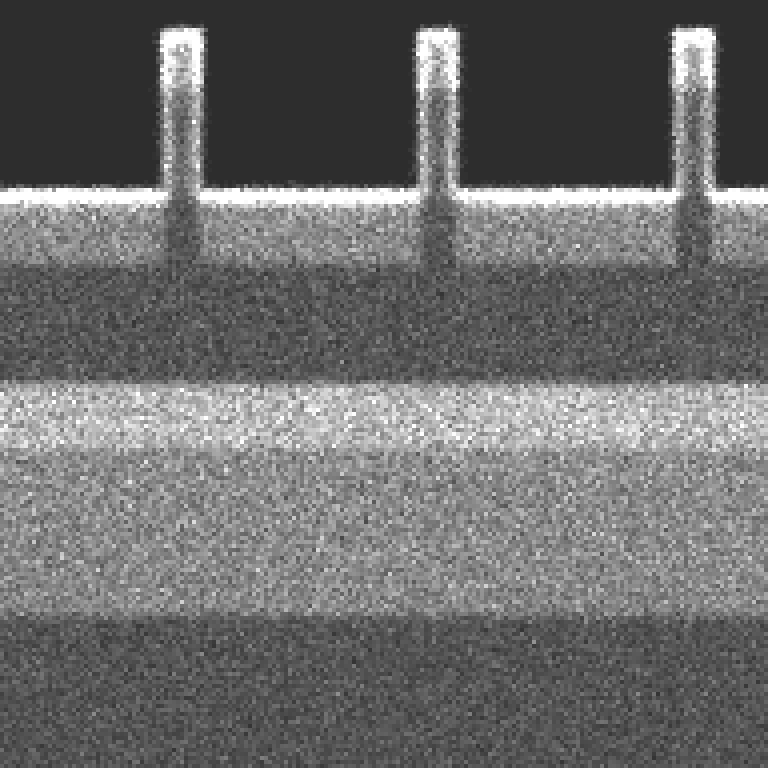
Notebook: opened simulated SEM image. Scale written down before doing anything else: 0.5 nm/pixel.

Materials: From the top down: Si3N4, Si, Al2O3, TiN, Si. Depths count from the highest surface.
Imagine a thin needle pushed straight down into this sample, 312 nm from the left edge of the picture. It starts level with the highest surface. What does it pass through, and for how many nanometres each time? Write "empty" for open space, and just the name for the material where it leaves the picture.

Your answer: empty 80, Si3N4 36, Si 60, Al2O3 32, TiN 84, Si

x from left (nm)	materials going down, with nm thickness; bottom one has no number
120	empty 80, Si3N4 36, Si 60, Al2O3 32, TiN 84, Si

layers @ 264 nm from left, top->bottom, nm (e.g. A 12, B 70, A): empty 80, Si3N4 36, Si 60, Al2O3 32, TiN 84, Si